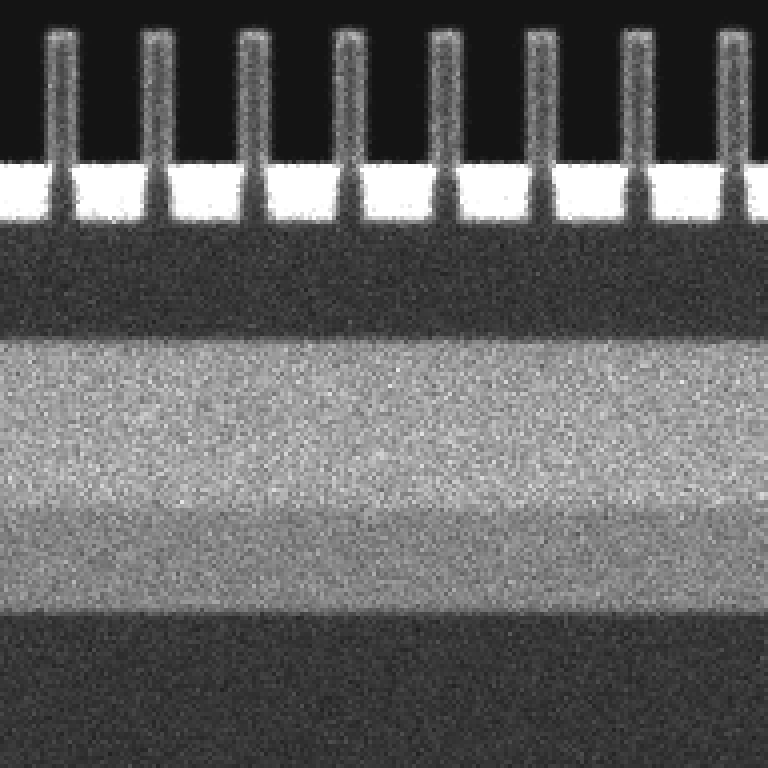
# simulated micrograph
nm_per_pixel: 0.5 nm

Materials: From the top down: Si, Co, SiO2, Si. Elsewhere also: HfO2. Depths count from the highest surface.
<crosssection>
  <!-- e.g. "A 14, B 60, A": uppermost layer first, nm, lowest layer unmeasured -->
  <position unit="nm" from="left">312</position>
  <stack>Si 154, Co 84, SiO2 52, Si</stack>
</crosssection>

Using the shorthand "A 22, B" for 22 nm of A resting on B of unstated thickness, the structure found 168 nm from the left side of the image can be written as Si 154, Co 84, SiO2 52, Si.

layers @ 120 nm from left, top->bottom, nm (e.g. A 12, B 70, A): Si 154, Co 84, SiO2 52, Si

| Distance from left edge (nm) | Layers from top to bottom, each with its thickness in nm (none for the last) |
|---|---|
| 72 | Si 154, Co 84, SiO2 52, Si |